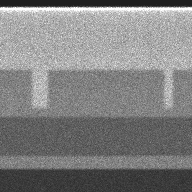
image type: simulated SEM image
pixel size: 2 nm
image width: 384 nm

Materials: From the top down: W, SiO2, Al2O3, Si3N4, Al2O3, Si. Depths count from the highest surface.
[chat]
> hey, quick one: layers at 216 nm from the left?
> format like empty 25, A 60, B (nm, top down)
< W 124, SiO2 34, Al2O3 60, Si3N4 78, Al2O3 26, Si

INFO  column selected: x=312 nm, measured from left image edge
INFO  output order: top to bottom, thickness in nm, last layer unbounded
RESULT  W 124, SiO2 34, Al2O3 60, Si3N4 78, Al2O3 26, Si